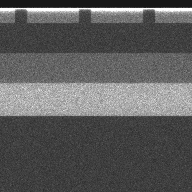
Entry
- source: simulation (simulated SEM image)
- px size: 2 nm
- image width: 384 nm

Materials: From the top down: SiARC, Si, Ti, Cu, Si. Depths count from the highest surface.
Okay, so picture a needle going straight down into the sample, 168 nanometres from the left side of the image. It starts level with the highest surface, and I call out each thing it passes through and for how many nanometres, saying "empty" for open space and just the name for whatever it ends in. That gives Si 90, Ti 60, Cu 66, Si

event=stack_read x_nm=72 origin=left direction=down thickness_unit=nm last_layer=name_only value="SiARC 30, Si 60, Ti 60, Cu 66, Si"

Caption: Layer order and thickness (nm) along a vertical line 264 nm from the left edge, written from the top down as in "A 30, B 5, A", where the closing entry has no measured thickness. SiARC 30, Si 60, Ti 60, Cu 66, Si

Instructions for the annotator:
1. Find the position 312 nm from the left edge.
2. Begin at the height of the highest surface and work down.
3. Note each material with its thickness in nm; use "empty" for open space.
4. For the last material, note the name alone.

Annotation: SiARC 30, Si 60, Ti 60, Cu 66, Si